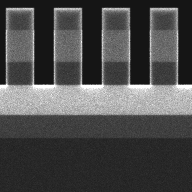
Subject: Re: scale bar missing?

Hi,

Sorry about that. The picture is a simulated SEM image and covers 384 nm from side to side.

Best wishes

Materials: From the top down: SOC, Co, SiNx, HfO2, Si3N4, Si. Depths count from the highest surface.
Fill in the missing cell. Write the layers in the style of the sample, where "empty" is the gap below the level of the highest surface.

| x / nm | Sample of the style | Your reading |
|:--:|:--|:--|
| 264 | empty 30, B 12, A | empty 154, HfO2 60, Si3N4 46, Si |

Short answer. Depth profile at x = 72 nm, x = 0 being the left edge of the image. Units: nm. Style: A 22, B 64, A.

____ empty 154, HfO2 60, Si3N4 46, Si